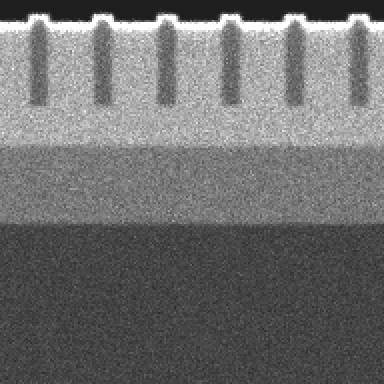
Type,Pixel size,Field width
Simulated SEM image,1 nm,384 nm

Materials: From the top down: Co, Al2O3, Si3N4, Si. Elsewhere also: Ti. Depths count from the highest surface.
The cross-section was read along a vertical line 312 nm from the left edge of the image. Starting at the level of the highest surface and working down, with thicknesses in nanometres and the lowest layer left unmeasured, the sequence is empty 8, Co 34, Al2O3 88, Si3N4 78, Si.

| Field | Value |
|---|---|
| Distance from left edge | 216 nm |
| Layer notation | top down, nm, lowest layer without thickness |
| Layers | empty 8, Co 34, Al2O3 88, Si3N4 78, Si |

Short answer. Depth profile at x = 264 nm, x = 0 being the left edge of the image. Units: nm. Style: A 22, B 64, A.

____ empty 8, Co 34, Al2O3 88, Si3N4 78, Si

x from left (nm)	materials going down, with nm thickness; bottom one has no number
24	empty 8, Co 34, Al2O3 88, Si3N4 78, Si